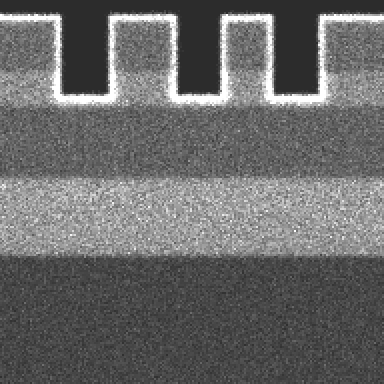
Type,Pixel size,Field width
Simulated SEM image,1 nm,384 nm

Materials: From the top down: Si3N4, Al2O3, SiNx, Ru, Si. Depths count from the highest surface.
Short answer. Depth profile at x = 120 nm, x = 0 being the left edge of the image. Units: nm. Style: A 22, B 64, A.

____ Si3N4 56, Al2O3 34, SiNx 72, Ru 78, Si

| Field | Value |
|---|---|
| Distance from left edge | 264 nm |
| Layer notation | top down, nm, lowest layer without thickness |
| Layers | Si3N4 56, Al2O3 34, SiNx 72, Ru 78, Si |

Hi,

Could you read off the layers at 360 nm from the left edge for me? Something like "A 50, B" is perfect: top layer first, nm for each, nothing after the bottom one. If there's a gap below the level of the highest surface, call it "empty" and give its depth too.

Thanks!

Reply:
Si3N4 56, Al2O3 34, SiNx 72, Ru 78, Si